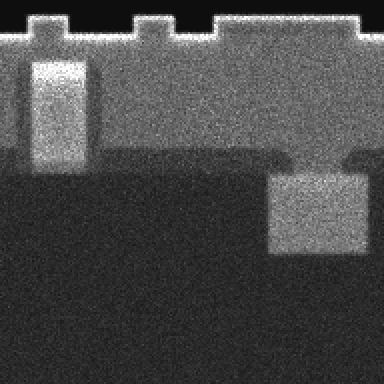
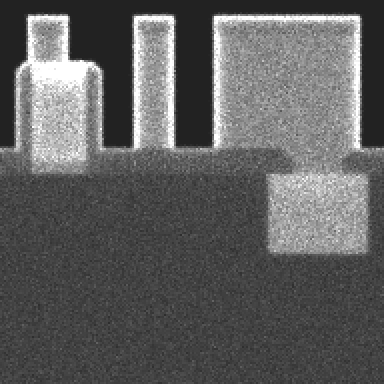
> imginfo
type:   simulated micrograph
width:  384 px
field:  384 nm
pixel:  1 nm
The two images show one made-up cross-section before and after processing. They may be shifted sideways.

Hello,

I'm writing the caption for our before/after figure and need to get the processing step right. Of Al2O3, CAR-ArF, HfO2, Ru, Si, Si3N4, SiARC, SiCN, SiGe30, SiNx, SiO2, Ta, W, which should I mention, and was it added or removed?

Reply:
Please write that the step removed SiO2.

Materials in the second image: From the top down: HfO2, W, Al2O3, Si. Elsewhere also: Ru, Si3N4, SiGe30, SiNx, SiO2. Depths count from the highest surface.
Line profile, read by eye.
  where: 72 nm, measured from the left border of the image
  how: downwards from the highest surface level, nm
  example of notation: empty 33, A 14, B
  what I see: empty 46, HfO2 16, W 84, Al2O3 12, Si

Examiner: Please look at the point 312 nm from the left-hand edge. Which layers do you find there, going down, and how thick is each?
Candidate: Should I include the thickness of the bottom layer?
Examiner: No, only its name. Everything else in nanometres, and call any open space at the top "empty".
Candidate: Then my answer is Si3N4 18, SiO2 140, Ru 80, Si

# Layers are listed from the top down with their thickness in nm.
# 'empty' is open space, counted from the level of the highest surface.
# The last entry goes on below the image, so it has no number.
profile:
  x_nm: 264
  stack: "Si3N4 18, SiO2 114, SiGe30 26, Si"